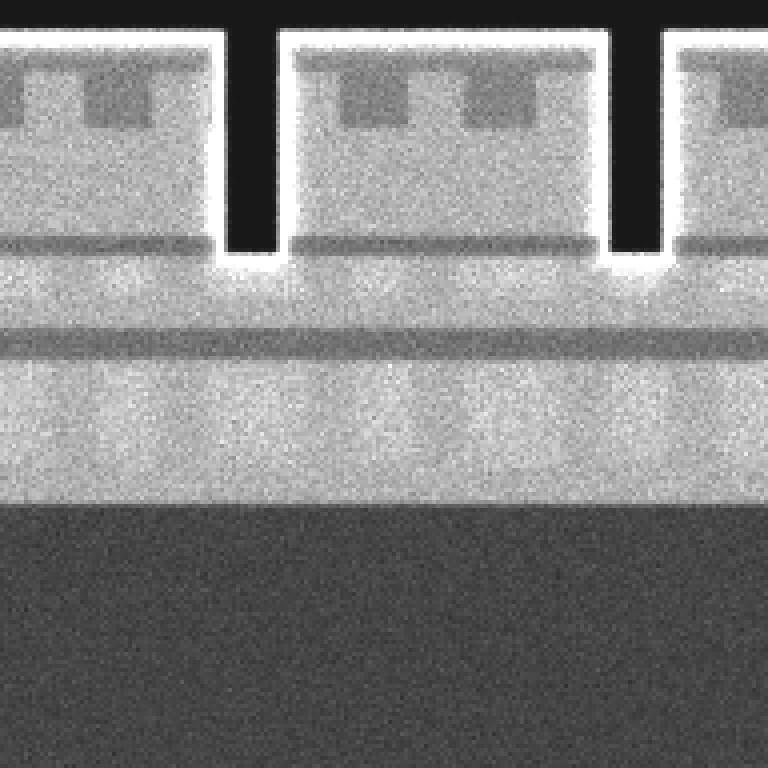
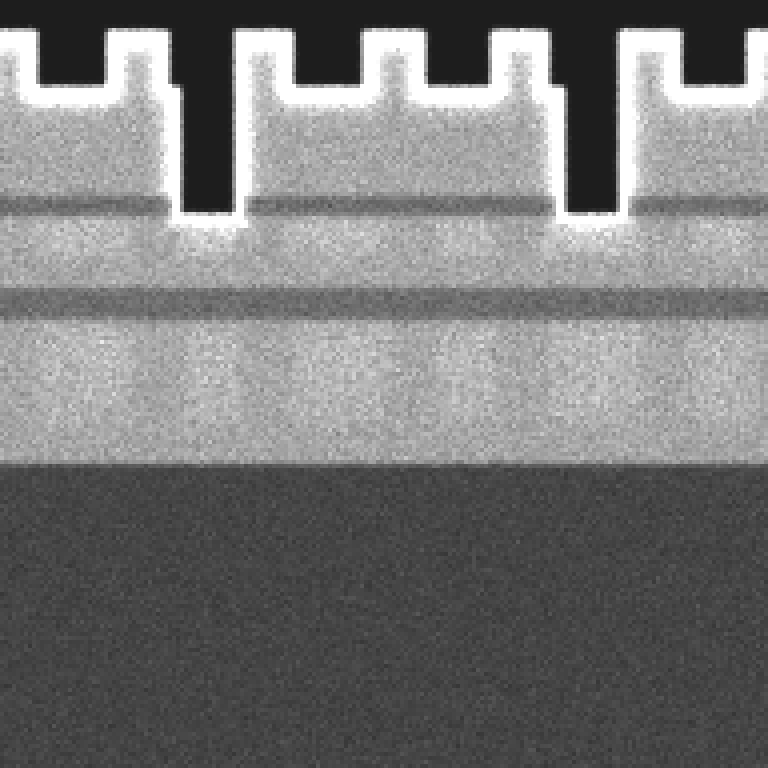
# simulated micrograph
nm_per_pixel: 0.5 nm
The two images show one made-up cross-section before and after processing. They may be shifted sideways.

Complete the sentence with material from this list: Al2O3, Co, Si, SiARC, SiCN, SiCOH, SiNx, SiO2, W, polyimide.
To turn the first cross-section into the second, SiARC must be removed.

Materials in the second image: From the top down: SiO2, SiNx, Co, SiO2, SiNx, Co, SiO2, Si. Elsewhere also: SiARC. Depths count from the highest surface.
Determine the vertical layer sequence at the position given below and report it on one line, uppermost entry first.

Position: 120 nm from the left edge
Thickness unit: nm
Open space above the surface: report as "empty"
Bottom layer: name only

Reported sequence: SiO2 82, SiNx 10, SiO2 36, SiNx 16, SiO2 72, Si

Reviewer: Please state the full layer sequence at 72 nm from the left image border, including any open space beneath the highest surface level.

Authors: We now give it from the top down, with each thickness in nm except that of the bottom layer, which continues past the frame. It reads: SiO2 82, SiNx 10, SiO2 36, SiNx 16, SiO2 72, Si